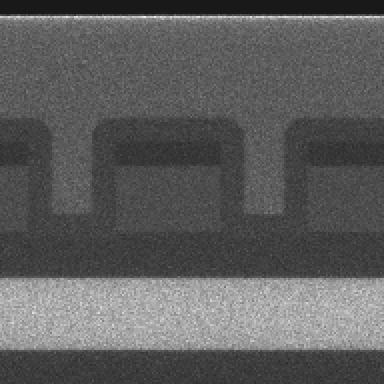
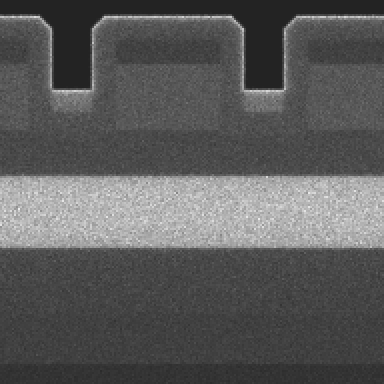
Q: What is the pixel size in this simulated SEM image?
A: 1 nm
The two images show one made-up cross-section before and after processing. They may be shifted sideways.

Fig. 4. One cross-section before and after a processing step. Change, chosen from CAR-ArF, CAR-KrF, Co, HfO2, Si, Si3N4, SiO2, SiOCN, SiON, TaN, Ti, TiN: Co removed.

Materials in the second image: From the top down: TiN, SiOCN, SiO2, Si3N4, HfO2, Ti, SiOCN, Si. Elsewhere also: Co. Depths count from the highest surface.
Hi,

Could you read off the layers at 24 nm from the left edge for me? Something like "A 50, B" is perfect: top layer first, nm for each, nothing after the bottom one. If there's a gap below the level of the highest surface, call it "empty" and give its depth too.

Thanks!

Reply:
TiN 24, SiOCN 24, SiO2 66, Si3N4 46, HfO2 72, Ti 66, SiOCN 50, Si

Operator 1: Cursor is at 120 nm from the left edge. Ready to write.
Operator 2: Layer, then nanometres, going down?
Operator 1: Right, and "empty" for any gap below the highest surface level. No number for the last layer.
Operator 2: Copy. TiN 24, SiOCN 24, SiO2 66, Si3N4 46, HfO2 72, Ti 66, SiOCN 50, Si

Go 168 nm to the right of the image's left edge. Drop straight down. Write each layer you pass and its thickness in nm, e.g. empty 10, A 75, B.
TiN 24, SiOCN 24, SiO2 66, Si3N4 46, HfO2 72, Ti 66, SiOCN 50, Si